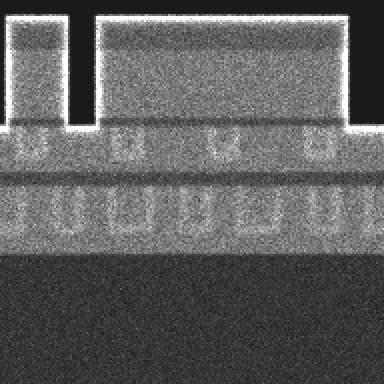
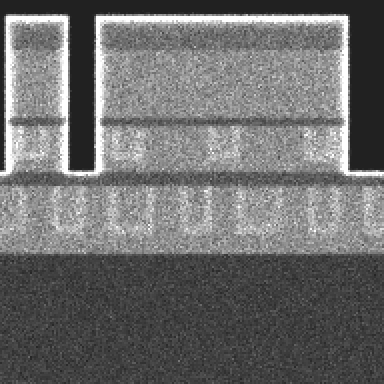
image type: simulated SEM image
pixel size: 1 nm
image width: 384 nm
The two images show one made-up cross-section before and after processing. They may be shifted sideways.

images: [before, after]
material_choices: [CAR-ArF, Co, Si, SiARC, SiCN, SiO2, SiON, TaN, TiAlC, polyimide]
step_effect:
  removed: SiO2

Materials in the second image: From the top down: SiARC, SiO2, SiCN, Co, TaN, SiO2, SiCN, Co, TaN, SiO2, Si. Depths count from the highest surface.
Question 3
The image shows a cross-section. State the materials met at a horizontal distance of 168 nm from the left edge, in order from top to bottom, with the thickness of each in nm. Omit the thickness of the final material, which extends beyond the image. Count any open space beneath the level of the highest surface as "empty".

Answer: SiARC 34, SiO2 68, SiCN 8, SiO2 46, SiCN 14, SiO2 68, Si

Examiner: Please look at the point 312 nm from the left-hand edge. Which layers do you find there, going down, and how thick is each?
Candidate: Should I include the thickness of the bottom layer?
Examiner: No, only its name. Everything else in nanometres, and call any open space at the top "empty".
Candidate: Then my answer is SiARC 34, SiO2 68, SiCN 8, Co 26, TaN 8, SiO2 12, SiCN 14, TaN 48, SiO2 20, Si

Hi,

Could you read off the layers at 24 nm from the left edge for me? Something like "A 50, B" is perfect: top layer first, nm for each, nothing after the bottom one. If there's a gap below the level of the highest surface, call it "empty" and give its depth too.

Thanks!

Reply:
SiARC 34, SiO2 68, SiCN 8, Co 26, TaN 8, SiO2 12, SiCN 14, TaN 48, SiO2 20, Si